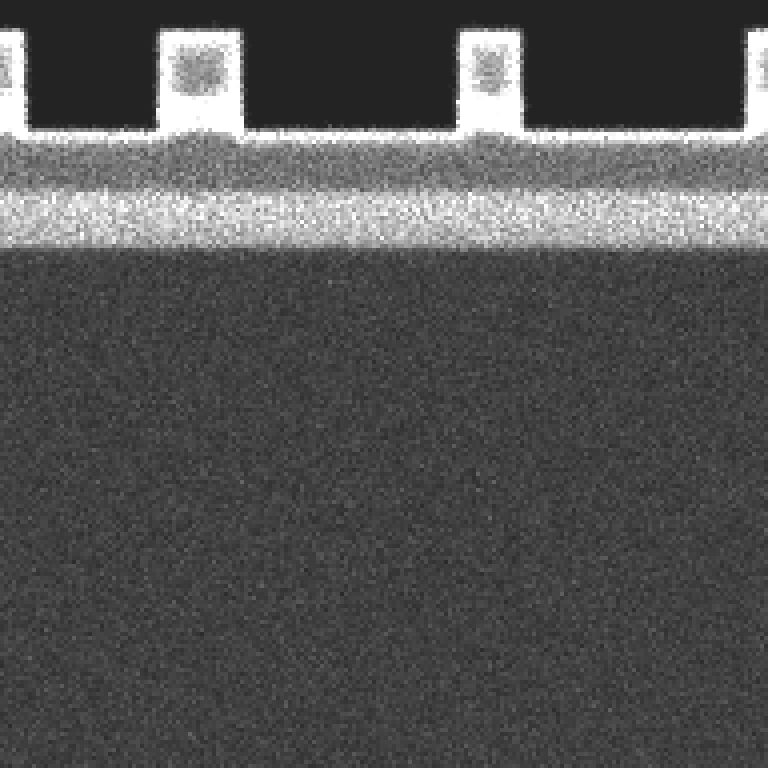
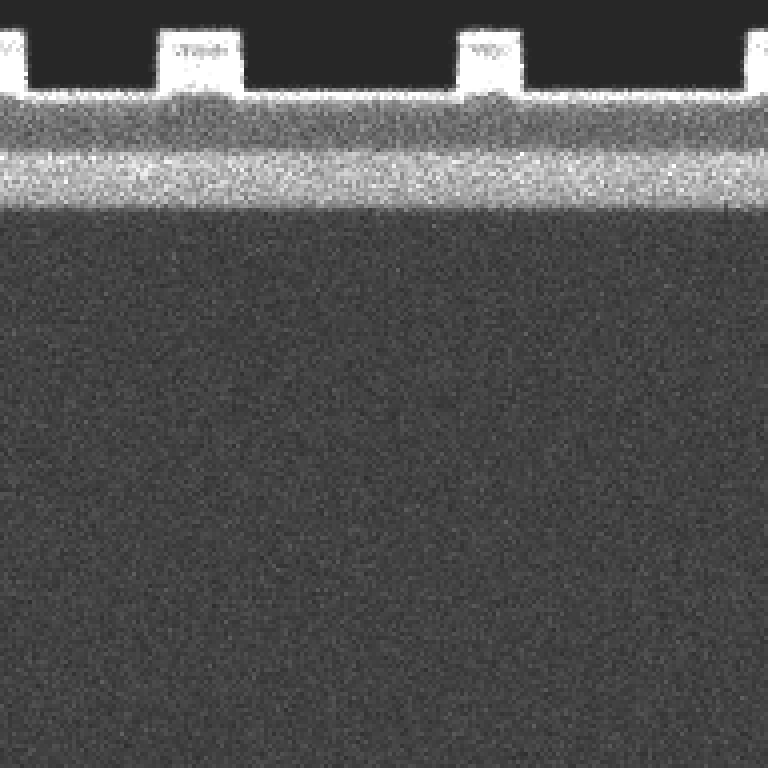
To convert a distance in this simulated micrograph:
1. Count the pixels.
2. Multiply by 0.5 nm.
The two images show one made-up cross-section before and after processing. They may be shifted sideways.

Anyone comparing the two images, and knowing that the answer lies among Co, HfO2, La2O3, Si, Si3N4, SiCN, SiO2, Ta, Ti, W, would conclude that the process removed SiO2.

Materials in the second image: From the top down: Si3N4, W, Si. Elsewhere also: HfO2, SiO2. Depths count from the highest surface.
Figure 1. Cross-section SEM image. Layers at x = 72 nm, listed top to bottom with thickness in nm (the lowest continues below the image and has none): empty 30, Si3N4 30, W 28, Si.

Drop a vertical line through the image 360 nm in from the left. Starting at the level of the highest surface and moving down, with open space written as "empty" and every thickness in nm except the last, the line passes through empty 30, Si3N4 30, W 28, Si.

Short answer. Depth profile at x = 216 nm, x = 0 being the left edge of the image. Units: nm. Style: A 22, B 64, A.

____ empty 30, Si3N4 30, W 28, Si